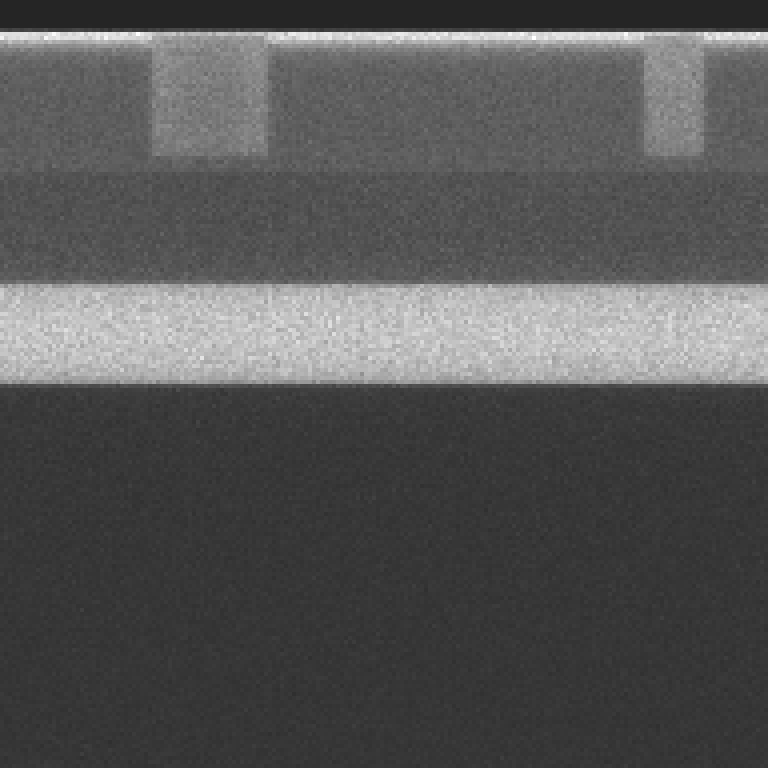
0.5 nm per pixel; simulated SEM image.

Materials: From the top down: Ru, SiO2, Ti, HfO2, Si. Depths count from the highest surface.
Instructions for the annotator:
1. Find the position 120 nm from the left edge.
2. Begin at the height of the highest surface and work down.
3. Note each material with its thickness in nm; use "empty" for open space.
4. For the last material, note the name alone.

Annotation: Ru 62, SiO2 8, Ti 56, HfO2 50, Si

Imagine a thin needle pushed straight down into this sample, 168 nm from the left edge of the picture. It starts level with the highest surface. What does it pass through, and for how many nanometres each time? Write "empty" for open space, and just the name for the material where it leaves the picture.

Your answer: SiO2 70, Ti 56, HfO2 50, Si